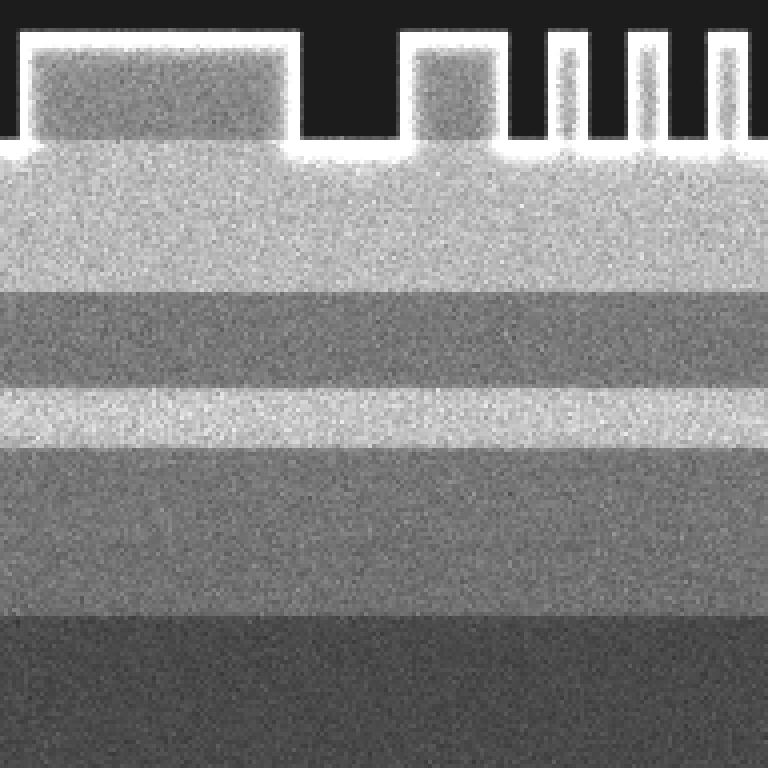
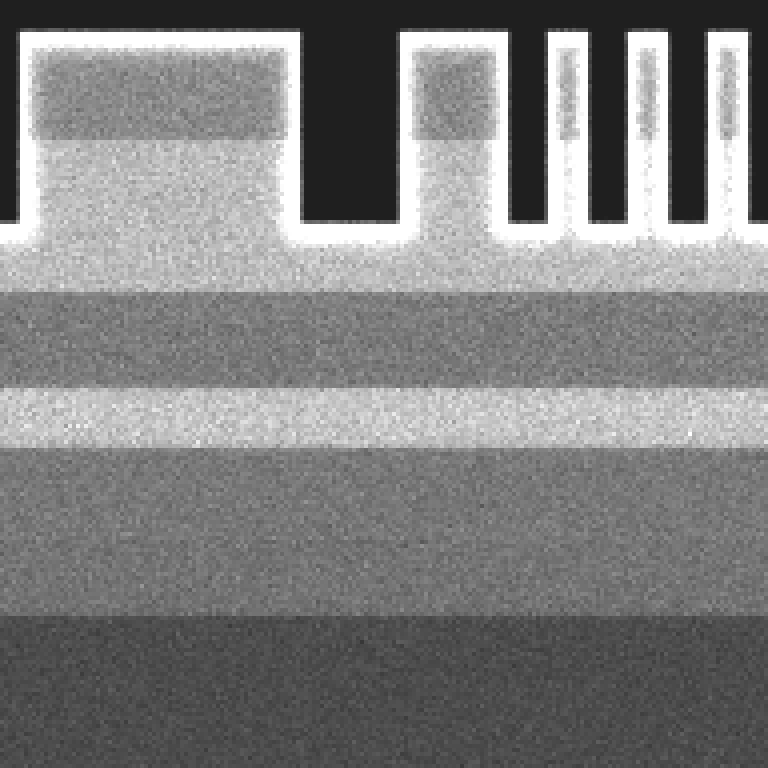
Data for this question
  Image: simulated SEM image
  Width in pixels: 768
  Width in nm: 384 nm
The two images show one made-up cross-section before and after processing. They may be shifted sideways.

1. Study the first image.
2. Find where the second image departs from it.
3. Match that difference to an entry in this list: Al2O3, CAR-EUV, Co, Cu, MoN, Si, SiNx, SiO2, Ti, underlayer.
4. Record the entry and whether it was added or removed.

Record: SiO2 / removed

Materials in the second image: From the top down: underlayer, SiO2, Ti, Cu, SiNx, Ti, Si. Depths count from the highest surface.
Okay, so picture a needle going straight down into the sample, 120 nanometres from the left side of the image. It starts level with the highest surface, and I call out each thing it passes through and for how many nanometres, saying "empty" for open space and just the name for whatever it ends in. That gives underlayer 54, SiO2 76, Ti 48, Cu 30, SiNx 46, Ti 38, Si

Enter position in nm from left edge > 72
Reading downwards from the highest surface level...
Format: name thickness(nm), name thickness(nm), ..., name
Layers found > underlayer 54, SiO2 76, Ti 48, Cu 30, SiNx 46, Ti 38, Si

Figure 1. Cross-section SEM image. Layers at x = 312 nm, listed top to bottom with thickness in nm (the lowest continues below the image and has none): empty 96, SiO2 34, Ti 48, Cu 30, SiNx 46, Ti 38, Si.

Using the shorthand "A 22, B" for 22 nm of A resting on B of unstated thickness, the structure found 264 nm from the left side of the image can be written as empty 96, SiO2 34, Ti 48, Cu 30, SiNx 46, Ti 38, Si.